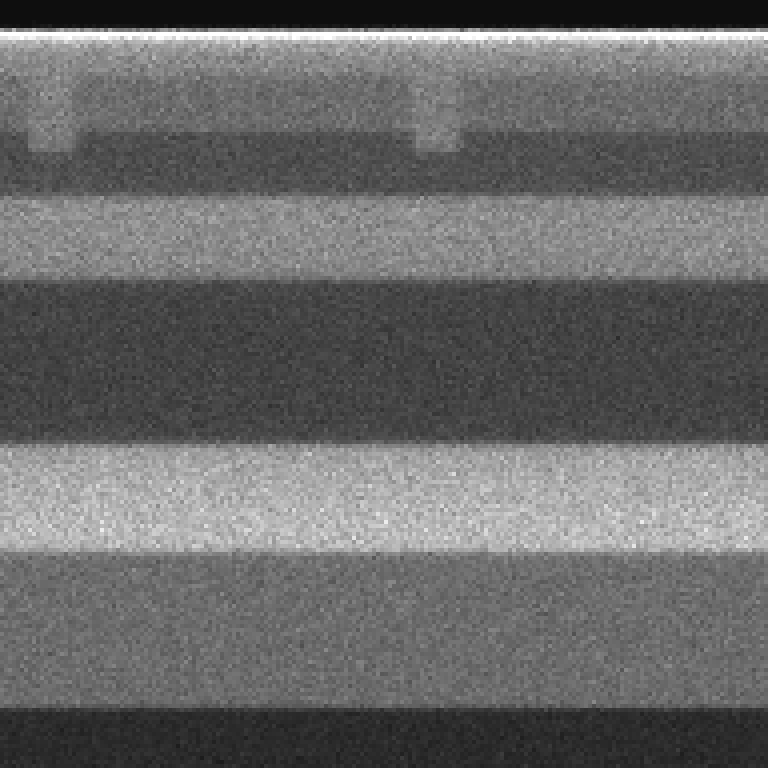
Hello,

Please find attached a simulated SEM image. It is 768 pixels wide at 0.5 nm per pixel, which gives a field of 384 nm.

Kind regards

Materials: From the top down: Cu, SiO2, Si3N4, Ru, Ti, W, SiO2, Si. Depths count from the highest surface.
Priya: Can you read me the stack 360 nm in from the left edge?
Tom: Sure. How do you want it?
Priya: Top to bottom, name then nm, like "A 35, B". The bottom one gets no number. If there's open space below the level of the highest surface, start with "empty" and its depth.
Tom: Cu 22, SiO2 28, Si3N4 32, Ru 42, Ti 82, W 54, SiO2 78, Si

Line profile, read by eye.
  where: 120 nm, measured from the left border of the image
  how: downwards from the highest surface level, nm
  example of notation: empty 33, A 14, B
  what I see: Cu 22, SiO2 28, Si3N4 32, Ru 42, Ti 82, W 54, SiO2 78, Si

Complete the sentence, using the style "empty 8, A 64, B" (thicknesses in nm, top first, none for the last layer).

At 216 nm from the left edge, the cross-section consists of Cu 60, Si3N4 22, Ru 42, Ti 82, W 54, SiO2 78, Si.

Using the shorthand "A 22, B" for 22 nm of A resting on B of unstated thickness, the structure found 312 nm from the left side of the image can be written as Cu 22, SiO2 28, Si3N4 32, Ru 42, Ti 82, W 54, SiO2 78, Si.